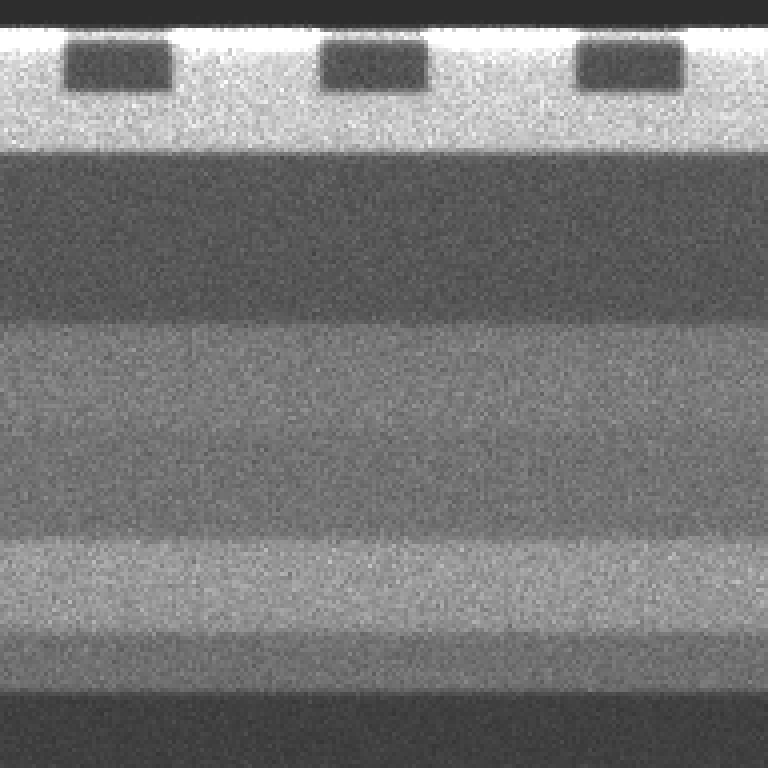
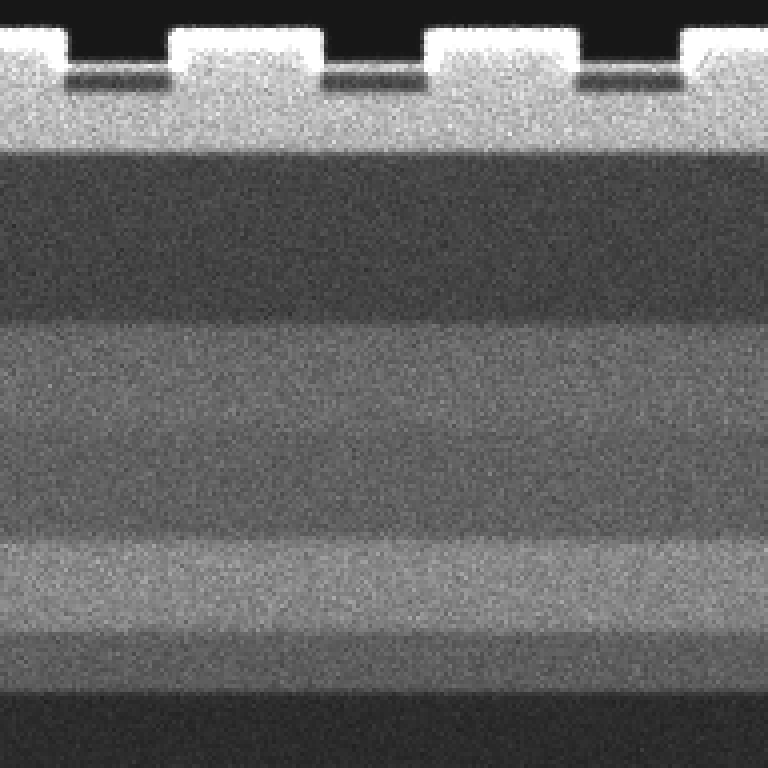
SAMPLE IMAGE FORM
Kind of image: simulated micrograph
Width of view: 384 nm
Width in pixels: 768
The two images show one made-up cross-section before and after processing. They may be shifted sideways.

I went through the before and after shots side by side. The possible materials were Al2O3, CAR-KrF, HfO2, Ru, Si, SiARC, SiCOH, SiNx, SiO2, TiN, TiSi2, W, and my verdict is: removed, SiNx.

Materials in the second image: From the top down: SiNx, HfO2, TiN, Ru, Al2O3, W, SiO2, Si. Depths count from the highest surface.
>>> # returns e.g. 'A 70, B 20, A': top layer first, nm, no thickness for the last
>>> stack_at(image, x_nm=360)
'HfO2 60, TiN 86, Ru 52, Al2O3 56, W 46, SiO2 30, Si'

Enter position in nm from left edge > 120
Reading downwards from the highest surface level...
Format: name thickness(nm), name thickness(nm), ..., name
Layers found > HfO2 60, TiN 86, Ru 52, Al2O3 56, W 46, SiO2 30, Si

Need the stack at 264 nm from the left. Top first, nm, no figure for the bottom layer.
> HfO2 60, TiN 86, Ru 52, Al2O3 56, W 46, SiO2 30, Si